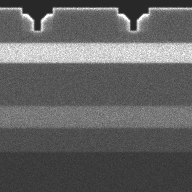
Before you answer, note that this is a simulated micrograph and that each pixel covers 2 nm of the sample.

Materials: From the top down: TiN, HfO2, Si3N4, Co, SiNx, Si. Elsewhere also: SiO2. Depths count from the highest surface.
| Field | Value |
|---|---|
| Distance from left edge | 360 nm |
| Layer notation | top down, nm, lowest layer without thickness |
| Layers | TiN 70, HfO2 40, Si3N4 86, Co 44, SiNx 48, Si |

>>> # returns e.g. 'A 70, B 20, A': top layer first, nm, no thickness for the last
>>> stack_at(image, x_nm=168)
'TiN 70, HfO2 40, Si3N4 86, Co 44, SiNx 48, Si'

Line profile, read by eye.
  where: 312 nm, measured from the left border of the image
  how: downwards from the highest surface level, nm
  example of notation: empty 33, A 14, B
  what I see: TiN 70, HfO2 40, Si3N4 86, Co 44, SiNx 48, Si